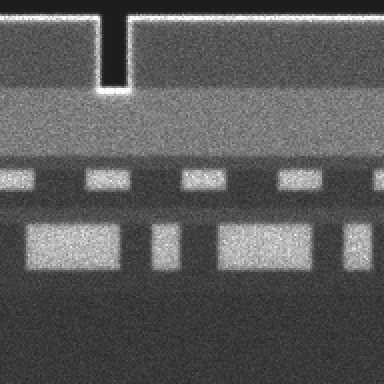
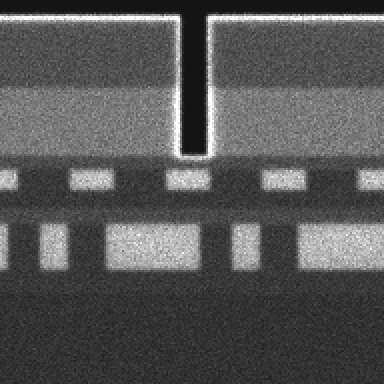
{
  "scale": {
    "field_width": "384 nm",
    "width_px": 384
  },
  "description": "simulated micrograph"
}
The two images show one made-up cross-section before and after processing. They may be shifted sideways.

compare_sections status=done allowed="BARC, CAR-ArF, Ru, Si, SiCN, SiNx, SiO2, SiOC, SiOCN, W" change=removed material="SiO2"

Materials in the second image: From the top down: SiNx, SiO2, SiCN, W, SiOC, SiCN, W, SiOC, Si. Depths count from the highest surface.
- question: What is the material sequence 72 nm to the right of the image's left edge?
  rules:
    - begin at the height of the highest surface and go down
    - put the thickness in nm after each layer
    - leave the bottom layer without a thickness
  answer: SiNx 72, SiO2 68, SiCN 14, W 20, SiOC 18, SiCN 16, SiOC 70, Si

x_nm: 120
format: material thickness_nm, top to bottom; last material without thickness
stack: SiNx 72, SiO2 68, SiCN 14, SiOC 38, SiCN 16, W 46, SiOC 24, Si